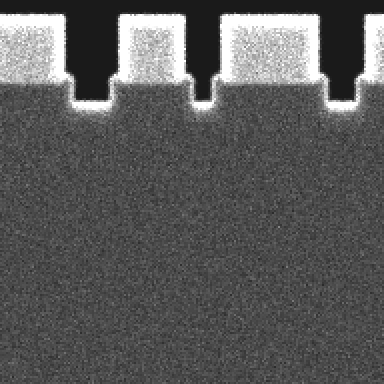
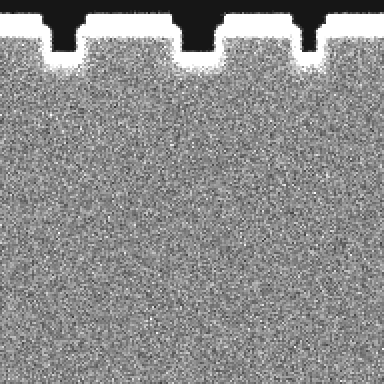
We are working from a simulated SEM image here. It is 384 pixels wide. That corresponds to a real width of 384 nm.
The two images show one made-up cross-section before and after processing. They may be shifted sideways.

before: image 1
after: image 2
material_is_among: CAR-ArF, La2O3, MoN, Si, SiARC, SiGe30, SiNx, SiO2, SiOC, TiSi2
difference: SiO2, removed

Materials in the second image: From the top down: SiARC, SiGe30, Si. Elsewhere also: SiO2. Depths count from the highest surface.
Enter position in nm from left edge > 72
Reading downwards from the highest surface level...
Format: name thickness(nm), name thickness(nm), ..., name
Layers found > empty 38, SiARC 10, SiGe30 10, Si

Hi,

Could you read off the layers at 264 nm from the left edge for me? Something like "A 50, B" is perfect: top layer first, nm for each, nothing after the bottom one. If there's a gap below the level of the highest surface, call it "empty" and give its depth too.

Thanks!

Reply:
SiO2 20, Si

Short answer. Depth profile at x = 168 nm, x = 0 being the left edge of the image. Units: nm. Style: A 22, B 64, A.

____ SiO2 20, Si